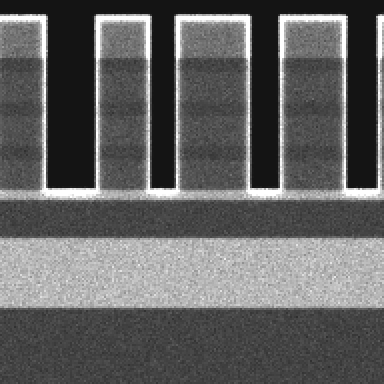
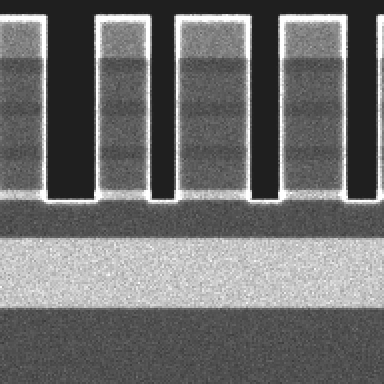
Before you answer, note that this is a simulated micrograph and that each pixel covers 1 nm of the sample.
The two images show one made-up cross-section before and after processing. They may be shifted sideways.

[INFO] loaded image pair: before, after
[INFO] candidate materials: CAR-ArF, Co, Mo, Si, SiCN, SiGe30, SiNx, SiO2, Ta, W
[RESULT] removed Co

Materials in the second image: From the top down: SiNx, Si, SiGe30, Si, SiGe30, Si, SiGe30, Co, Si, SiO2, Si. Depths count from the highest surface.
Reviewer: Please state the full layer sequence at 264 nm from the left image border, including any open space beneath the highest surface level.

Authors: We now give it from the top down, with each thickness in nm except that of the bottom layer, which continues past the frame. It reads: empty 184, Si 38, SiO2 70, Si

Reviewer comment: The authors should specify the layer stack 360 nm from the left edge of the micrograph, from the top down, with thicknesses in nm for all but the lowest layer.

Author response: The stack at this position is empty 184, Si 38, SiO2 70, Si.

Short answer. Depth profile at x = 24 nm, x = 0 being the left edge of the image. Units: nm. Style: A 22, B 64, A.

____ SiNx 42, Si 14, SiGe30 30, Si 14, SiGe30 30, Si 14, SiGe30 30, Co 10, Si 38, SiO2 70, Si